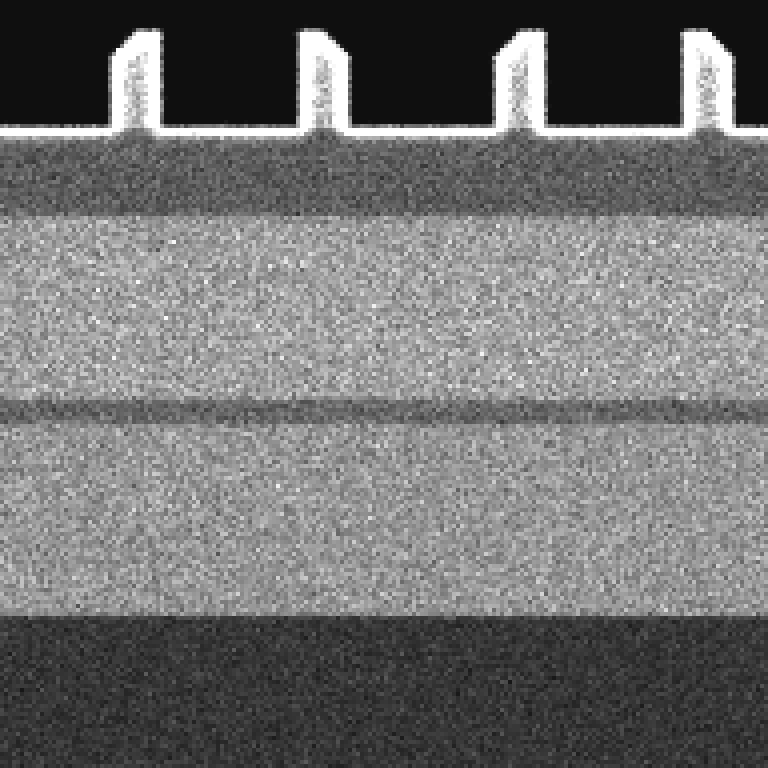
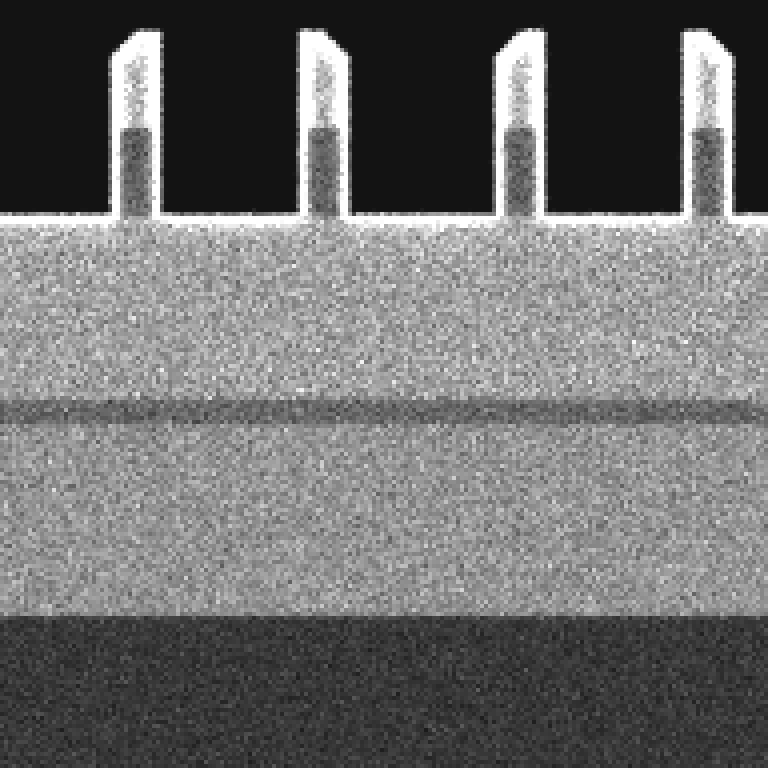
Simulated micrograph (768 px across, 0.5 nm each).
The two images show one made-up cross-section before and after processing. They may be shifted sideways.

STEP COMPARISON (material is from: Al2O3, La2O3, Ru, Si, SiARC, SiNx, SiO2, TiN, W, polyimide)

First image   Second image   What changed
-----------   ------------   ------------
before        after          SiNx, removed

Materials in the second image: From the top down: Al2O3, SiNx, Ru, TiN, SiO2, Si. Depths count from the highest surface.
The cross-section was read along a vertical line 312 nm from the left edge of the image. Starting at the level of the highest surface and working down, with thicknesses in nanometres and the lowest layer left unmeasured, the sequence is empty 92, Ru 92, TiN 12, SiO2 96, Si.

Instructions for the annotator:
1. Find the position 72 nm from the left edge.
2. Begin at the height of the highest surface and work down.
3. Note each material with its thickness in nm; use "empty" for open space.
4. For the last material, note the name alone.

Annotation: Al2O3 48, SiNx 44, Ru 92, TiN 12, SiO2 96, Si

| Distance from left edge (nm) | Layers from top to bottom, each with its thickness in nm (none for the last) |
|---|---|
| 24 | empty 92, Ru 92, TiN 12, SiO2 96, Si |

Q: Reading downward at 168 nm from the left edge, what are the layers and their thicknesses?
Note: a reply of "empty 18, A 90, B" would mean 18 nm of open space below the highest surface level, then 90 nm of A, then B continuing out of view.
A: empty 8, Al2O3 40, SiNx 44, Ru 92, TiN 12, SiO2 96, Si